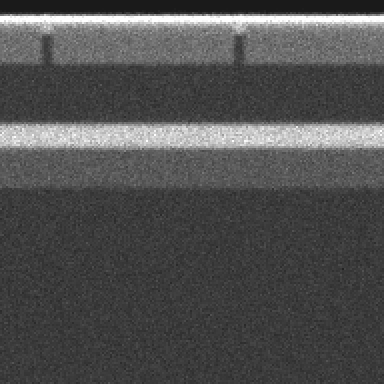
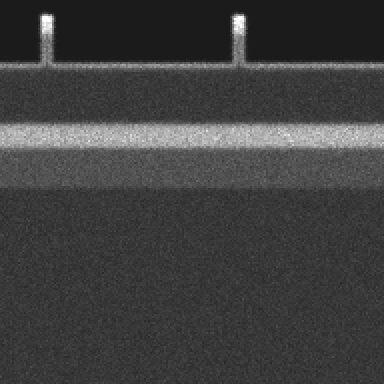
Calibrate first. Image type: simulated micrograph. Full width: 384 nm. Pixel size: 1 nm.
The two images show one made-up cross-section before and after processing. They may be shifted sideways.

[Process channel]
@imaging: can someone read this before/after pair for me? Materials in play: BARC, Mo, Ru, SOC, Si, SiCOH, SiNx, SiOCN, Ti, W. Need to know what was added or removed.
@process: SOC removed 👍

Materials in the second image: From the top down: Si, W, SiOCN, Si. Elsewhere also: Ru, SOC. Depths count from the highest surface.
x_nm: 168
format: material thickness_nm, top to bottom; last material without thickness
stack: empty 48, Si 60, W 24, SiOCN 40, Si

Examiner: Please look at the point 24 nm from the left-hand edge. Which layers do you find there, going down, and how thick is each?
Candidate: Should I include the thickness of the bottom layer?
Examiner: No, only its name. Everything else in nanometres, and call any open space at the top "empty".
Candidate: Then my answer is empty 48, Si 60, W 24, SiOCN 40, Si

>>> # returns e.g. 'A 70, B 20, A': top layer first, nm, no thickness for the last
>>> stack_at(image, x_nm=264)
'empty 48, Si 60, W 24, SiOCN 40, Si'